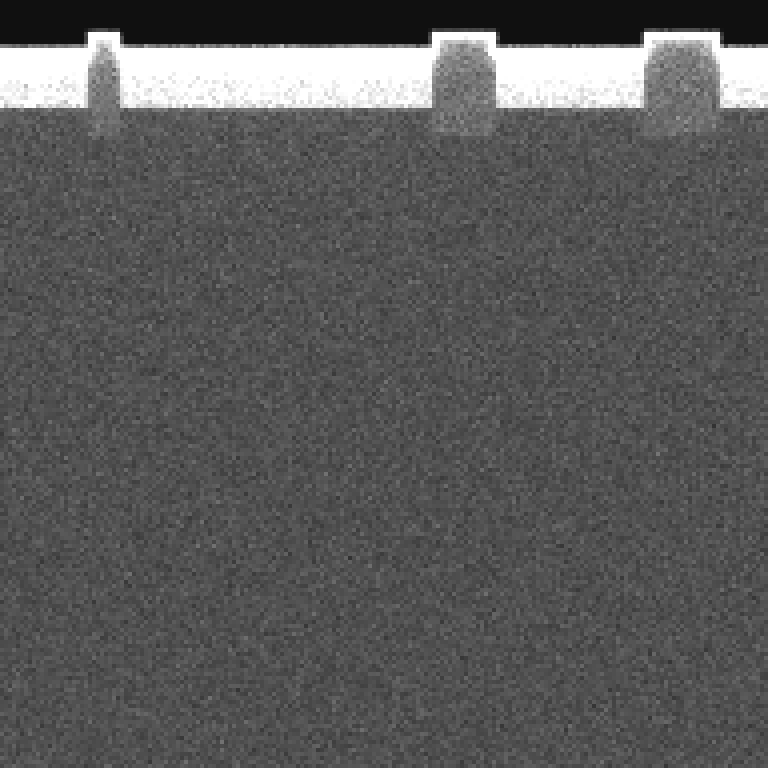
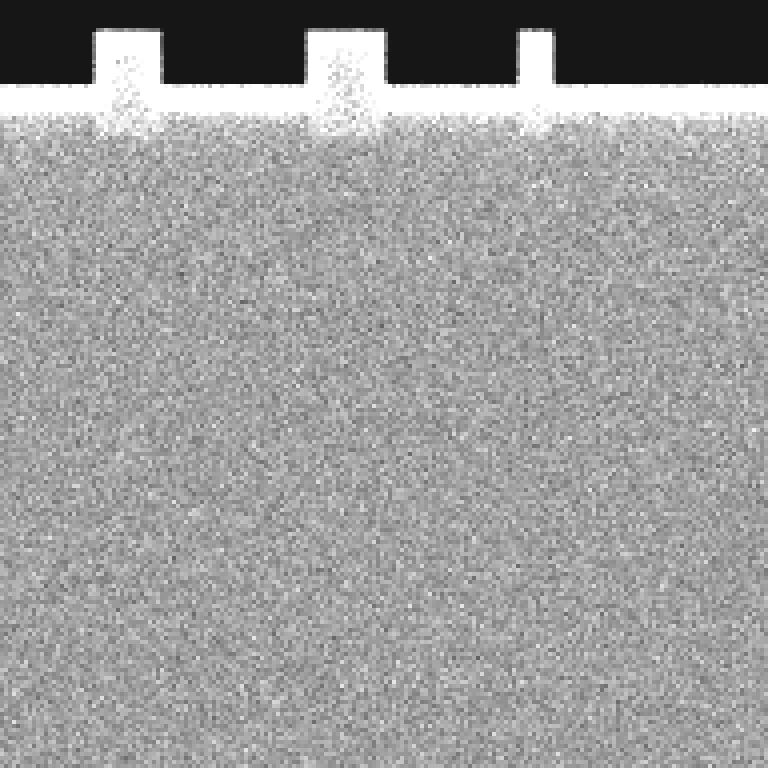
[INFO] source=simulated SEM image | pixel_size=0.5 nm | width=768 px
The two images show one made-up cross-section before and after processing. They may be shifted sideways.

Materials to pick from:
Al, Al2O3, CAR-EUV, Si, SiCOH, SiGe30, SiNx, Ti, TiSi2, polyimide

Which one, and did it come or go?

Al2O3 - removed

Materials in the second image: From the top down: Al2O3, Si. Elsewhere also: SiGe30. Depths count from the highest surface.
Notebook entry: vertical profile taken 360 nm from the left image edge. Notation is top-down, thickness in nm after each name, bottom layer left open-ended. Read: empty 28, Al2O3 10, Si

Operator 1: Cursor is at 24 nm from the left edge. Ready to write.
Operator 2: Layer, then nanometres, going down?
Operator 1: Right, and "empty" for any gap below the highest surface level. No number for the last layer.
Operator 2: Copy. empty 28, Al2O3 10, Si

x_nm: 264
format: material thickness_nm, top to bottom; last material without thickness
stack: SiGe30 52, Si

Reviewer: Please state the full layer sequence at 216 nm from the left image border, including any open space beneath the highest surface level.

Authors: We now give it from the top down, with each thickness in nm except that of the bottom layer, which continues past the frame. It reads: empty 28, Al2O3 10, Si